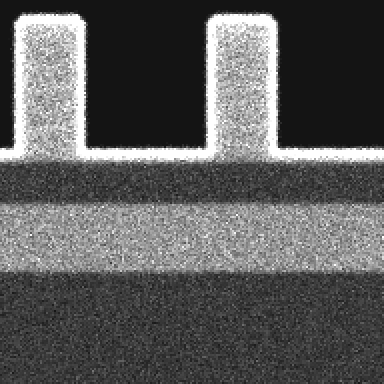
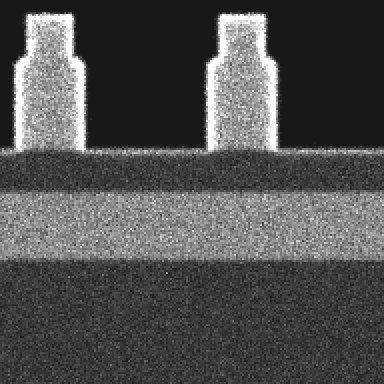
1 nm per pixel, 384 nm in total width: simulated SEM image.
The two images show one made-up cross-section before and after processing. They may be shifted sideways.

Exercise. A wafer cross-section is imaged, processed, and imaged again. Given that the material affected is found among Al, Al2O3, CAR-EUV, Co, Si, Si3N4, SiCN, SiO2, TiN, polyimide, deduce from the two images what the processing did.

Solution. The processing removed SiO2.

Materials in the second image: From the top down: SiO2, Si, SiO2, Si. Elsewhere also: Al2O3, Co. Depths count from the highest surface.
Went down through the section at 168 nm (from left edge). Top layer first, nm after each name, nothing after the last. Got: empty 134, Si 42, SiO2 68, Si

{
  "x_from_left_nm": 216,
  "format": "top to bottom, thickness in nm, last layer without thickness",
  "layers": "empty 42, SiO2 92, Si 42, SiO2 68, Si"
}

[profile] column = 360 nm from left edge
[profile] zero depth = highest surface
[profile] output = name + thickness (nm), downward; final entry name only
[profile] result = empty 134, Si 42, SiO2 68, Si